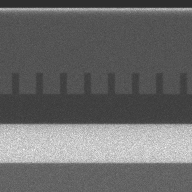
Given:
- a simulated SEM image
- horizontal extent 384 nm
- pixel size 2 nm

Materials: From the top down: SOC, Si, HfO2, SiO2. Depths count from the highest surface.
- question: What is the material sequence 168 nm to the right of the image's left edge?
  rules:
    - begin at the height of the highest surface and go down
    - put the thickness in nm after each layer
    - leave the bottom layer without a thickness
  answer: SOC 130, Si 102, HfO2 78, SiO2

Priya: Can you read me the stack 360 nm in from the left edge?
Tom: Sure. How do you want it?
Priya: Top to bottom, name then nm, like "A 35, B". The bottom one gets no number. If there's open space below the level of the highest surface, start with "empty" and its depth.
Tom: SOC 130, Si 102, HfO2 78, SiO2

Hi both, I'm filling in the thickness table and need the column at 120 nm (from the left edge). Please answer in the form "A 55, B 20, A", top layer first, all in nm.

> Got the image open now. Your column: SOC 130, Si 102, HfO2 78, SiO2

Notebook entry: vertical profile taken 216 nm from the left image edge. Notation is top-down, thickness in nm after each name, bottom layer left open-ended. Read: SOC 130, Si 102, HfO2 78, SiO2